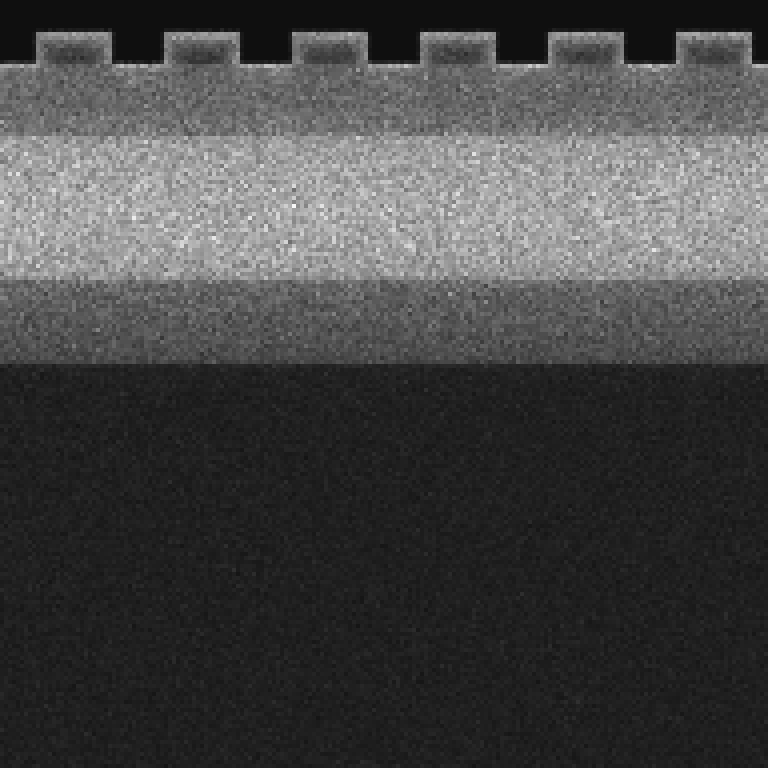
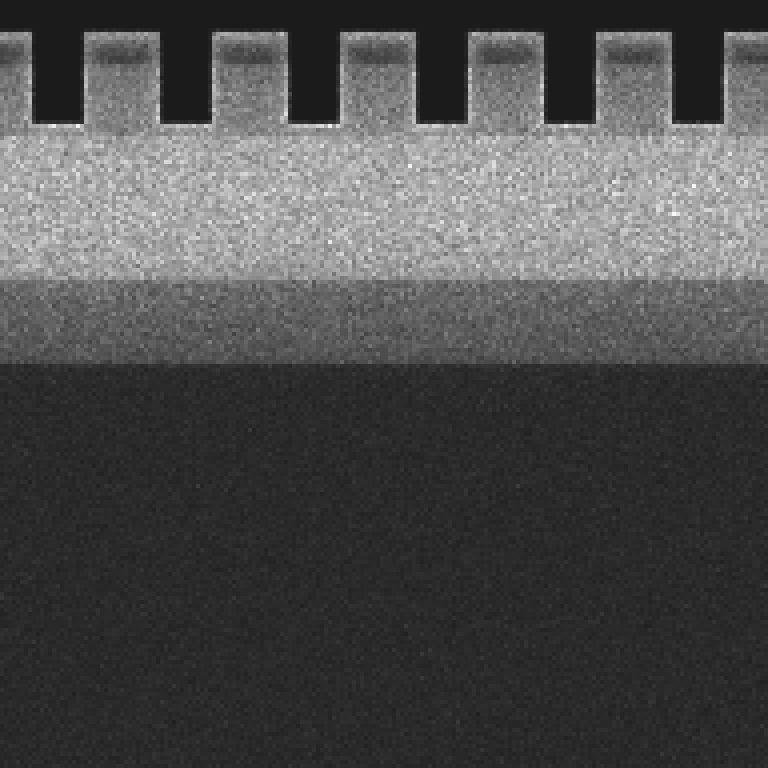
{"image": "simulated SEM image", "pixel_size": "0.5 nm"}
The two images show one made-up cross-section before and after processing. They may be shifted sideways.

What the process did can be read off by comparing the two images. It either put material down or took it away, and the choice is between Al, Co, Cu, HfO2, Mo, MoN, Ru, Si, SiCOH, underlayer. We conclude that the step removed Ru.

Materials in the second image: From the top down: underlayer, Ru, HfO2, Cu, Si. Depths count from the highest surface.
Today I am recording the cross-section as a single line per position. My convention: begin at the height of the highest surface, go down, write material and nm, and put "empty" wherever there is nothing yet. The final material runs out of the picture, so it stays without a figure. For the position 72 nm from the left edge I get underlayer 16, Ru 36, HfO2 72, Cu 42, Si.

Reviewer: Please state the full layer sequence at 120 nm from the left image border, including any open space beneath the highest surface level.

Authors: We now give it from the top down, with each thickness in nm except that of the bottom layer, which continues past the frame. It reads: underlayer 16, Ru 36, HfO2 72, Cu 42, Si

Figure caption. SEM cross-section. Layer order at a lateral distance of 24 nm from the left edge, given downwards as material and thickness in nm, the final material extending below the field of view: empty 46, Ru 6, HfO2 72, Cu 42, Si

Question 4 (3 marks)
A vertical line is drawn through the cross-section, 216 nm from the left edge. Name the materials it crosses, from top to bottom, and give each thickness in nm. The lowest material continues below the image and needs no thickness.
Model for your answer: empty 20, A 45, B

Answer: empty 46, Ru 6, HfO2 72, Cu 42, Si